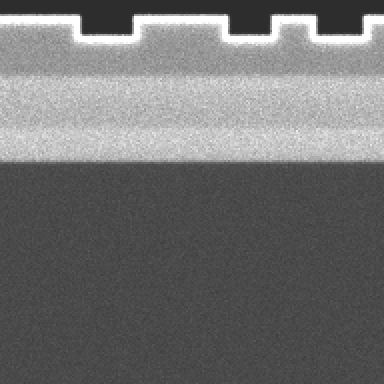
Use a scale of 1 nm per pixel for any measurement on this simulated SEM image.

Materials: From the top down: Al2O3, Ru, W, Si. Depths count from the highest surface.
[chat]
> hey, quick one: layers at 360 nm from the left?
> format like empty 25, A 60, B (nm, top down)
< empty 20, Al2O3 40, Ru 52, W 34, Si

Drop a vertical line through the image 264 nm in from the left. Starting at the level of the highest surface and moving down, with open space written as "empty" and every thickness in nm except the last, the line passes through empty 20, Al2O3 40, Ru 52, W 34, Si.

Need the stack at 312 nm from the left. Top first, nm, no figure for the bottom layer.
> Al2O3 60, Ru 52, W 34, Si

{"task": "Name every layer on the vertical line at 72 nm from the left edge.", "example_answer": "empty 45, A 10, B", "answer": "Al2O3 60, Ru 52, W 34, Si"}